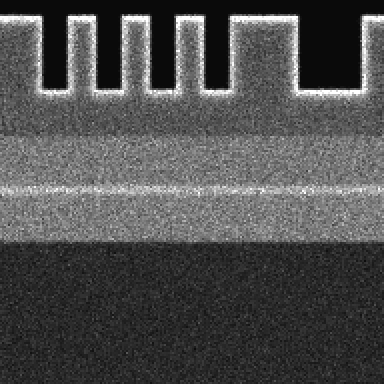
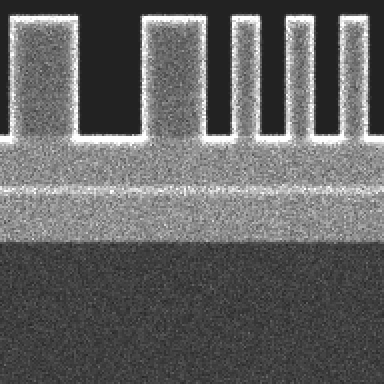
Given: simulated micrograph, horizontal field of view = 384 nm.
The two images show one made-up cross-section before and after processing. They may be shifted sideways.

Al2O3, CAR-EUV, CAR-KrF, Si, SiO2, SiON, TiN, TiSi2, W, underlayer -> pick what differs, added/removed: underlayer removed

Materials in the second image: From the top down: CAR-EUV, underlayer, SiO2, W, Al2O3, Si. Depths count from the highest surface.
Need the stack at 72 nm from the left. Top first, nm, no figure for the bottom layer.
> CAR-EUV 74, underlayer 46, SiO2 50, W 8, Al2O3 48, Si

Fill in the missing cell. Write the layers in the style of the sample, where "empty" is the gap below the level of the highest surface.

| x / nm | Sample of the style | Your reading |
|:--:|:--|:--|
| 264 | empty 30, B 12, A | empty 120, SiO2 50, W 8, Al2O3 48, Si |